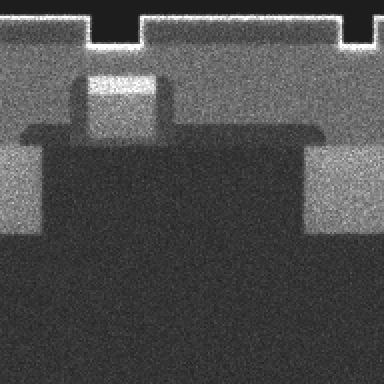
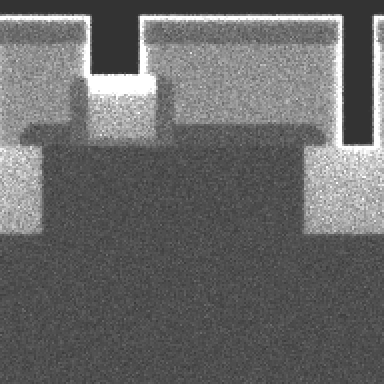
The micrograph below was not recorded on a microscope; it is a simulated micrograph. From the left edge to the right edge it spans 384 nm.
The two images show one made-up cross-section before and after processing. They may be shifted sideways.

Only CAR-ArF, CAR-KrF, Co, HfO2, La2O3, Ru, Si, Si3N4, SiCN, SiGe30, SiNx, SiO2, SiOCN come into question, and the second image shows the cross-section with SiO2 removed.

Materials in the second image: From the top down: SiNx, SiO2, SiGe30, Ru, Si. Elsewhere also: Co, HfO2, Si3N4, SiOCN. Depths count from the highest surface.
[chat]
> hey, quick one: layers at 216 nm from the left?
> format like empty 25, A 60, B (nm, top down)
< SiNx 28, SiO2 80, SiGe30 22, Si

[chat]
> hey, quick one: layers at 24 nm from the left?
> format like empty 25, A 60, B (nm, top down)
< SiNx 28, SiO2 86, SiGe30 16, Ru 88, Si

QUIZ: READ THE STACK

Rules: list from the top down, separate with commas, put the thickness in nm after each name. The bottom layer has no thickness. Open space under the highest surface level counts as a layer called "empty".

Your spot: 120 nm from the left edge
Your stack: empty 60, HfO2 18, Co 44, Si3N4 8, Si